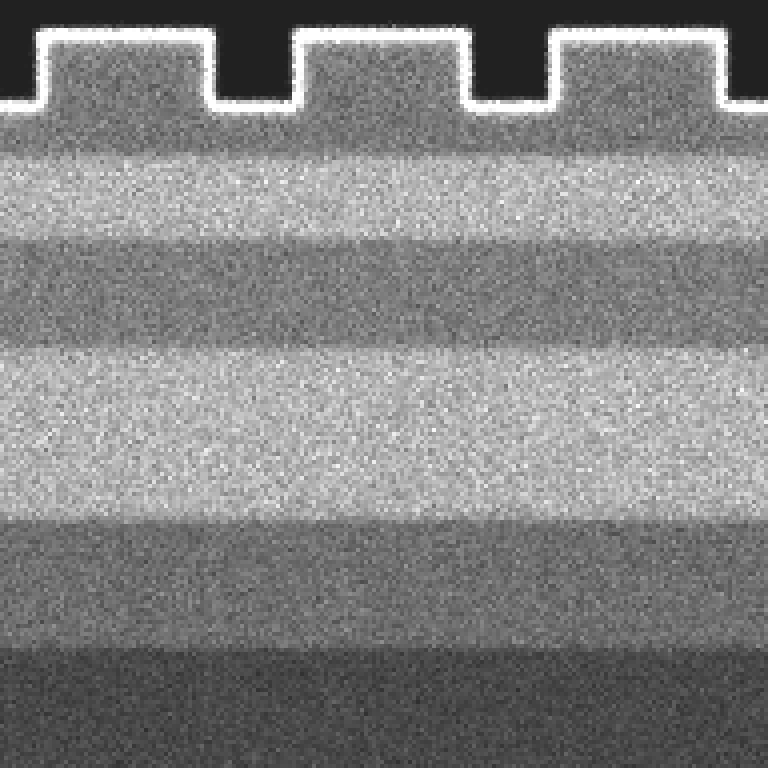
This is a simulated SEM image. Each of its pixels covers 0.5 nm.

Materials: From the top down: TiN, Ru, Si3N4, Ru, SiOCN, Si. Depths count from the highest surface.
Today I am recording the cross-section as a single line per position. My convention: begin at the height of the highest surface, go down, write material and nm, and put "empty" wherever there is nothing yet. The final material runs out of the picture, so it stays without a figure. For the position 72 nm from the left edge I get TiN 62, Ru 42, Si3N4 54, Ru 86, SiOCN 64, Si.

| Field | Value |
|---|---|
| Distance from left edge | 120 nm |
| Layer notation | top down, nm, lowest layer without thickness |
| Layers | empty 36, TiN 26, Ru 42, Si3N4 54, Ru 86, SiOCN 64, Si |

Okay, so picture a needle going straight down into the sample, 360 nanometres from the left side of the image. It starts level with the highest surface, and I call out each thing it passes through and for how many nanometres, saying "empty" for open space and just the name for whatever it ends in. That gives TiN 62, Ru 42, Si3N4 54, Ru 86, SiOCN 64, Si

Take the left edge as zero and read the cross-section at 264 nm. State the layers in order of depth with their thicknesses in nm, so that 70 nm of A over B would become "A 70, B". empty 36, TiN 26, Ru 42, Si3N4 54, Ru 86, SiOCN 64, Si